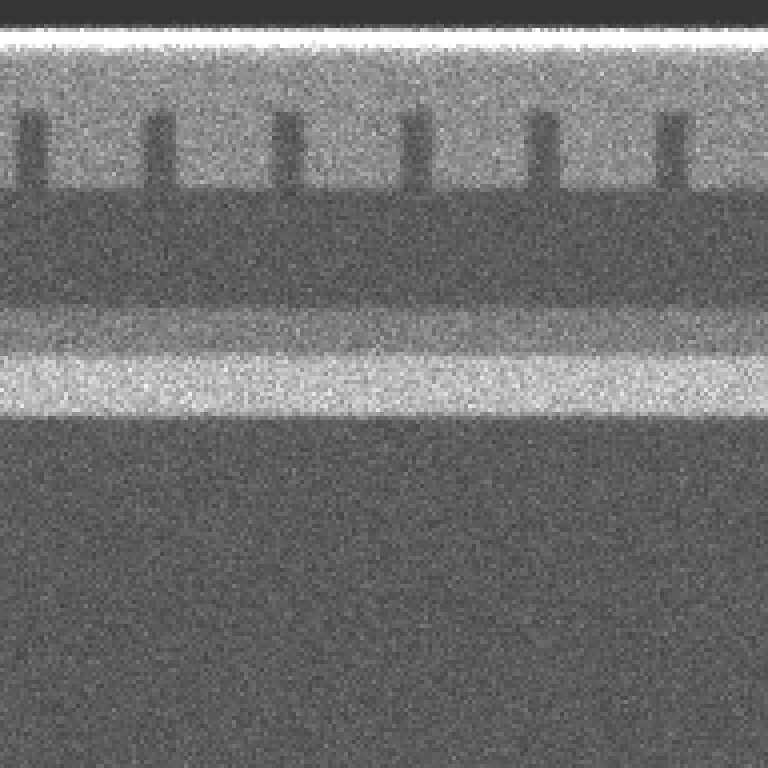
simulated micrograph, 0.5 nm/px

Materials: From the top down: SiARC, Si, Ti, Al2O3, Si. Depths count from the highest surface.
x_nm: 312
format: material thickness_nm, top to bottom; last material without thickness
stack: SiARC 78, Si 60, Ti 24, Al2O3 30, Si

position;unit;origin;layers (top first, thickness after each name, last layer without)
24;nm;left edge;SiARC 78, Si 60, Ti 24, Al2O3 30, Si